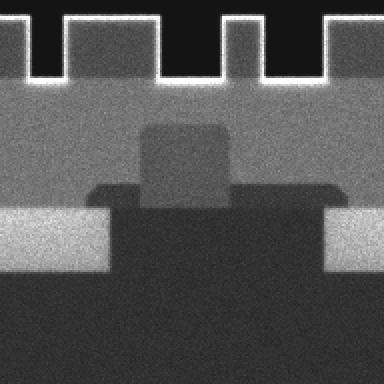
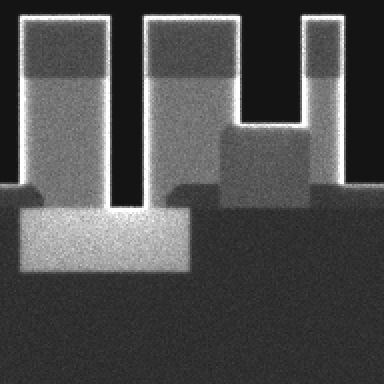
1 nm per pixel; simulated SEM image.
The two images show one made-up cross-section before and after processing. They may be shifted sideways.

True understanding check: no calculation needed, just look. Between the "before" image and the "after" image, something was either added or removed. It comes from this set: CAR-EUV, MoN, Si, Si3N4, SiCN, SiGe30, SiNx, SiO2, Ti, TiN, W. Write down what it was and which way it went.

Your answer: SiO2 (removed)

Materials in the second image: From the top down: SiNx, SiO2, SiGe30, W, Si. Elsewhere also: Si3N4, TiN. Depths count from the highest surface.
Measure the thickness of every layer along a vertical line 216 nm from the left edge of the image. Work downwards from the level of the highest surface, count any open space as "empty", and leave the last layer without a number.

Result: SiNx 62, SiO2 106, SiGe30 24, Si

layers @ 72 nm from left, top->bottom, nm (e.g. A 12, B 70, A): SiNx 62, SiO2 130, W 64, Si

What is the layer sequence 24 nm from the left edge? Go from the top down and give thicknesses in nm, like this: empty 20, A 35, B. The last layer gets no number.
SiNx 62, SiO2 106, SiGe30 24, W 64, Si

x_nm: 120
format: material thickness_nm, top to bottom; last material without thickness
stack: empty 192, W 64, Si